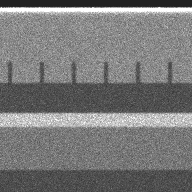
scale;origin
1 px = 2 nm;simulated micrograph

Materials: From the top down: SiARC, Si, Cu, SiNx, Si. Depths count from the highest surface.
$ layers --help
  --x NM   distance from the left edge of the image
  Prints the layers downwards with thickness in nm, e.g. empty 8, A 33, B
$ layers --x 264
SiARC 150, Si 60, Cu 28, SiNx 86, Si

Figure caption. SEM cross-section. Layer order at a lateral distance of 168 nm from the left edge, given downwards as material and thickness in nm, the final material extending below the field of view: SiARC 150, Si 60, Cu 28, SiNx 86, Si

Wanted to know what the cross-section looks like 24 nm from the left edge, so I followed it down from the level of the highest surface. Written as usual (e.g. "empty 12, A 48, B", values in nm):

SiARC 150, Si 60, Cu 28, SiNx 86, Si